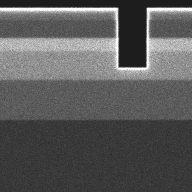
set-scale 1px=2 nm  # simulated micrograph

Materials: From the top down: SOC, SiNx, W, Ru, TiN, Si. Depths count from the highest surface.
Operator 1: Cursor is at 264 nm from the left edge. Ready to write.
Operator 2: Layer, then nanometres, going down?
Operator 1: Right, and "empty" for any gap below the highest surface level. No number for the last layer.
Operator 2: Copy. empty 120, Ru 24, TiN 80, Si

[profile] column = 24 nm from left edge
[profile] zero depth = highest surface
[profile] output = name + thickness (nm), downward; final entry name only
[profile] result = SOC 24, SiNx 36, W 26, Ru 58, TiN 80, Si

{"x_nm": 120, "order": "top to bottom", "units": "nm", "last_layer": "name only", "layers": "SOC 24, SiNx 36, W 26, Ru 58, TiN 80, Si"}